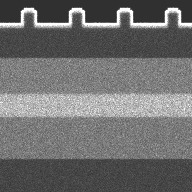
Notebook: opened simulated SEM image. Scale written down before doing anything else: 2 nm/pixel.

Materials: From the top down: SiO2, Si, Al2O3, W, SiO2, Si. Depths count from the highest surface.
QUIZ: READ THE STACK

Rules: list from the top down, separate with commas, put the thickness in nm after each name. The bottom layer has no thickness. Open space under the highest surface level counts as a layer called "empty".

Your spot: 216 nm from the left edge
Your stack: empty 30, SiO2 10, Si 60, Al2O3 72, W 46, SiO2 84, Si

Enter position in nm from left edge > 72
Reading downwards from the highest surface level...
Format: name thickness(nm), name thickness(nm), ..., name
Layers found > empty 6, SiO2 34, Si 60, Al2O3 72, W 46, SiO2 84, Si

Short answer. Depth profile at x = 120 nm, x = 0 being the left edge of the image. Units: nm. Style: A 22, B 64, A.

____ empty 30, SiO2 10, Si 60, Al2O3 72, W 46, SiO2 84, Si